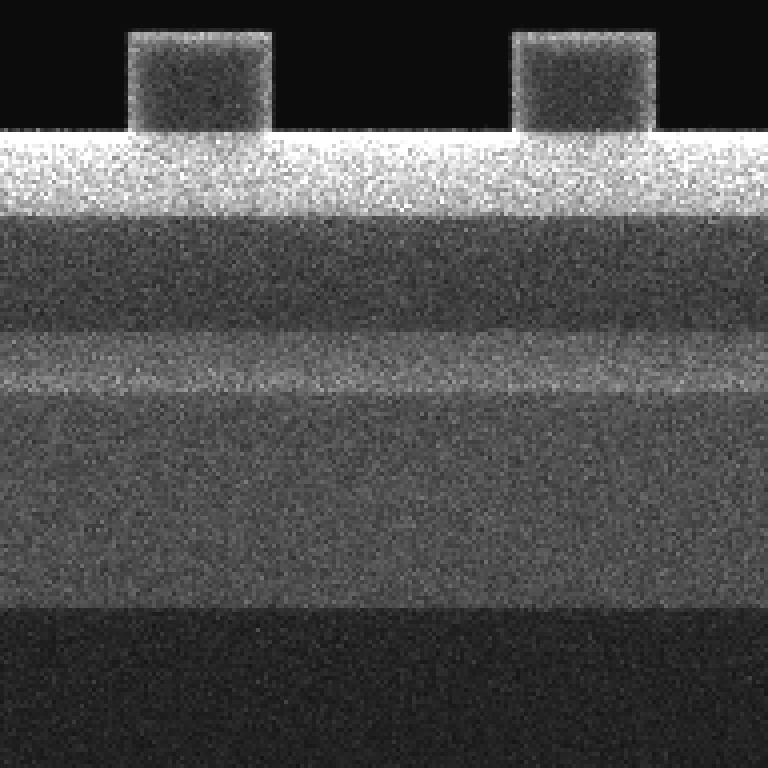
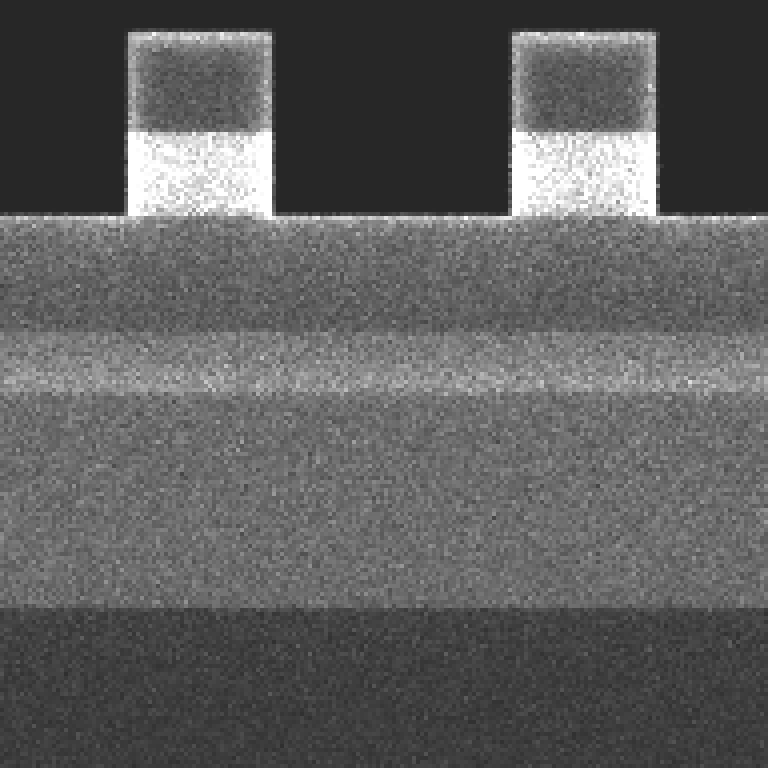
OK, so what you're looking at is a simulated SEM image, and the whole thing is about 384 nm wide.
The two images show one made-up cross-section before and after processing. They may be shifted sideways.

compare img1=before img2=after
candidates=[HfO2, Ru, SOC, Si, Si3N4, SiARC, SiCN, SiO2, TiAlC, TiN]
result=removed:HfO2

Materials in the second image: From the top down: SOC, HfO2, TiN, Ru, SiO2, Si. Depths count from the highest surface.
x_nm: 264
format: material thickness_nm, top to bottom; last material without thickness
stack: SOC 50, HfO2 42, TiN 58, Ru 30, SiO2 108, Si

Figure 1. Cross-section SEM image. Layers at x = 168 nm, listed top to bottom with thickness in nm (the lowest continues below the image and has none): empty 92, TiN 58, Ru 30, SiO2 108, Si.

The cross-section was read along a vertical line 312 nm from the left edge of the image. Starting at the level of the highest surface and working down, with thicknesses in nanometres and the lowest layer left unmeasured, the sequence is SOC 50, HfO2 42, TiN 58, Ru 30, SiO2 108, Si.